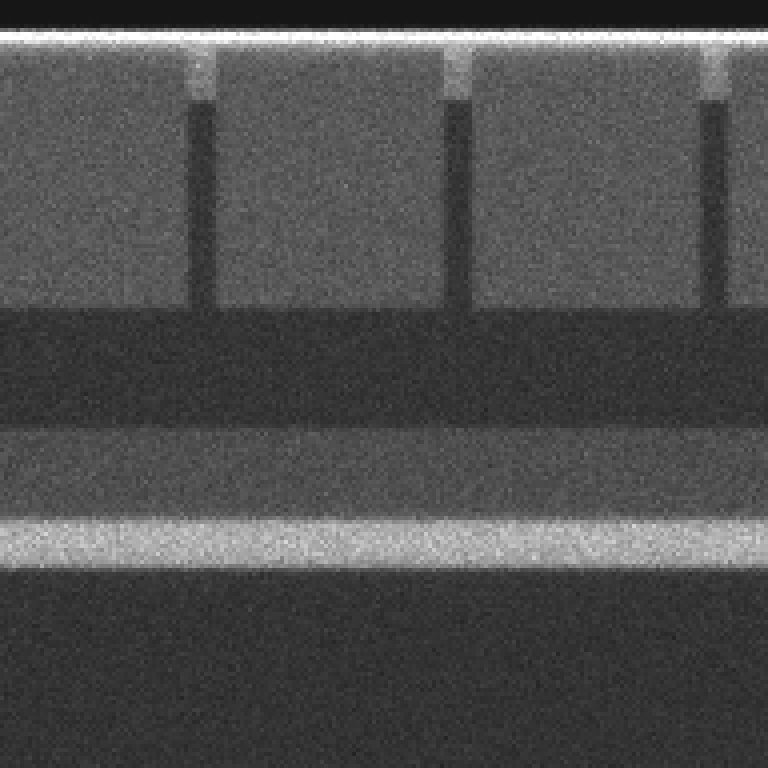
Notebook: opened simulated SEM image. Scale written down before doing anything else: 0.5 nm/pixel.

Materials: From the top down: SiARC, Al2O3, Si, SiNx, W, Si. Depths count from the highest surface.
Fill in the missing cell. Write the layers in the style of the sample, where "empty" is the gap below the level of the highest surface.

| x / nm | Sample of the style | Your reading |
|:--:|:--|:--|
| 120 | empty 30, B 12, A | SiARC 138, Si 60, SiNx 46, W 24, Si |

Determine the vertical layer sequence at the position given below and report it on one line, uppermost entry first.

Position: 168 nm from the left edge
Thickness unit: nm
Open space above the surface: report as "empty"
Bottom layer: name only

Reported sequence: SiARC 138, Si 60, SiNx 46, W 24, Si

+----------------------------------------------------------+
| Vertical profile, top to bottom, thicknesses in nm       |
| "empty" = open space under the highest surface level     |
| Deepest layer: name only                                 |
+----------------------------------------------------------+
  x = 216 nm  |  SiARC 138, Si 60, SiNx 46, W 24, Si